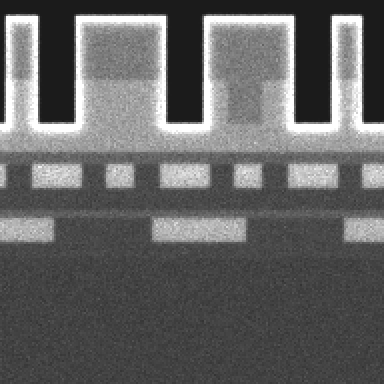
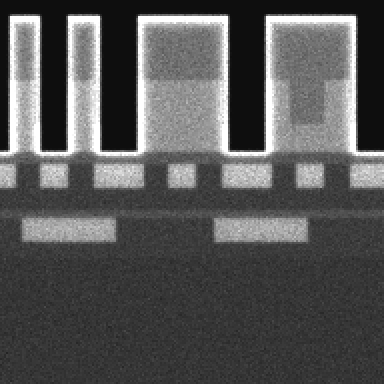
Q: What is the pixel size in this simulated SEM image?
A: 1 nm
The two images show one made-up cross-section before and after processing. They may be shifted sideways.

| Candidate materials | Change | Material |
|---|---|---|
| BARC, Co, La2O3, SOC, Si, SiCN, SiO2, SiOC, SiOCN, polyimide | removed | SiO2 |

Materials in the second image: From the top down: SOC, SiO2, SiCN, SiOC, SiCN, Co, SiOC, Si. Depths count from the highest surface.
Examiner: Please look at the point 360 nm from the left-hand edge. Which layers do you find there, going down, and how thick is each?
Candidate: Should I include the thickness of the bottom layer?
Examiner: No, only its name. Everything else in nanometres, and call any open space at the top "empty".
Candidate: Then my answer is empty 136, SiCN 12, Co 24, SiOC 22, SiCN 8, SiOC 40, Si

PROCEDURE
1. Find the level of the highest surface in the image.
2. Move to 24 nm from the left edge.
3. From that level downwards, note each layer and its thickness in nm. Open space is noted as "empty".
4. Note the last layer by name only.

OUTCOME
SOC 64, SiO2 72, SiCN 12, SiOC 46, SiCN 8, Co 24, SiOC 16, Si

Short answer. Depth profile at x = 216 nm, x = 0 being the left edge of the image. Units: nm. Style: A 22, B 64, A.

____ SOC 64, SiO2 72, SiCN 12, SiOC 46, SiCN 8, Co 24, SiOC 16, Si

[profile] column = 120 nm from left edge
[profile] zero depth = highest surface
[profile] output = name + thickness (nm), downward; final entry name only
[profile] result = empty 136, SiCN 12, Co 24, SiOC 22, SiCN 8, SiOC 40, Si